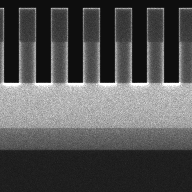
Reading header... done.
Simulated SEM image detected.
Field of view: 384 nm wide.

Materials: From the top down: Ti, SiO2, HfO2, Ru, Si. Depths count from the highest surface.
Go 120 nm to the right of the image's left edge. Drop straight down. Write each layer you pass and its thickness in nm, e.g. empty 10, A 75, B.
Ti 68, SiO2 82, HfO2 90, Ru 44, Si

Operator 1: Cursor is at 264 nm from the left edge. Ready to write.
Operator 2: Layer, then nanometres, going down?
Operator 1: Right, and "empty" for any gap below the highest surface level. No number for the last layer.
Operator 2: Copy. empty 150, HfO2 90, Ru 44, Si